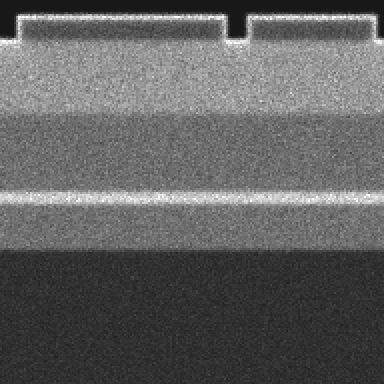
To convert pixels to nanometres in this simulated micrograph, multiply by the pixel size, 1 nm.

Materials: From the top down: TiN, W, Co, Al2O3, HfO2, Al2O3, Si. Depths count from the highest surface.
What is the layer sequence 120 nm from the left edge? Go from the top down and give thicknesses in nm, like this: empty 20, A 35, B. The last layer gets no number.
TiN 24, W 74, Co 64, Al2O3 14, HfO2 12, Al2O3 46, Si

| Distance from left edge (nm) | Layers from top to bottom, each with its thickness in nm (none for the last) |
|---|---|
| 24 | TiN 24, W 74, Co 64, Al2O3 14, HfO2 12, Al2O3 46, Si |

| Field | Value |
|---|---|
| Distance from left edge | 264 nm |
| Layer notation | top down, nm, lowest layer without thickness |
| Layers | TiN 24, W 74, Co 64, Al2O3 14, HfO2 12, Al2O3 46, Si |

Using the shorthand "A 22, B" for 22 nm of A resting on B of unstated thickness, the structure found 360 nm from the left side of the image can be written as TiN 24, W 74, Co 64, Al2O3 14, HfO2 12, Al2O3 46, Si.